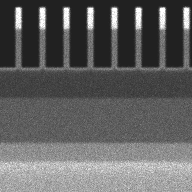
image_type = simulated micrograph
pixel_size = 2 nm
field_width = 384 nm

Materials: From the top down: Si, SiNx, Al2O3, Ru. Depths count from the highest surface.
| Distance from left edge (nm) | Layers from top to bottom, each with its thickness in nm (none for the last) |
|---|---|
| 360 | empty 120, Si 60, SiNx 90, Al2O3 38, Ru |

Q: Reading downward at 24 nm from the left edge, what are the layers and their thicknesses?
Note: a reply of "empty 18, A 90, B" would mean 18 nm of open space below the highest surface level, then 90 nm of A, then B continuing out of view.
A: empty 120, Si 60, SiNx 90, Al2O3 38, Ru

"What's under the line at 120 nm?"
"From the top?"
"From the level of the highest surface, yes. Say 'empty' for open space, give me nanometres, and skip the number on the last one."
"empty 120, Si 60, SiNx 90, Al2O3 38, Ru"